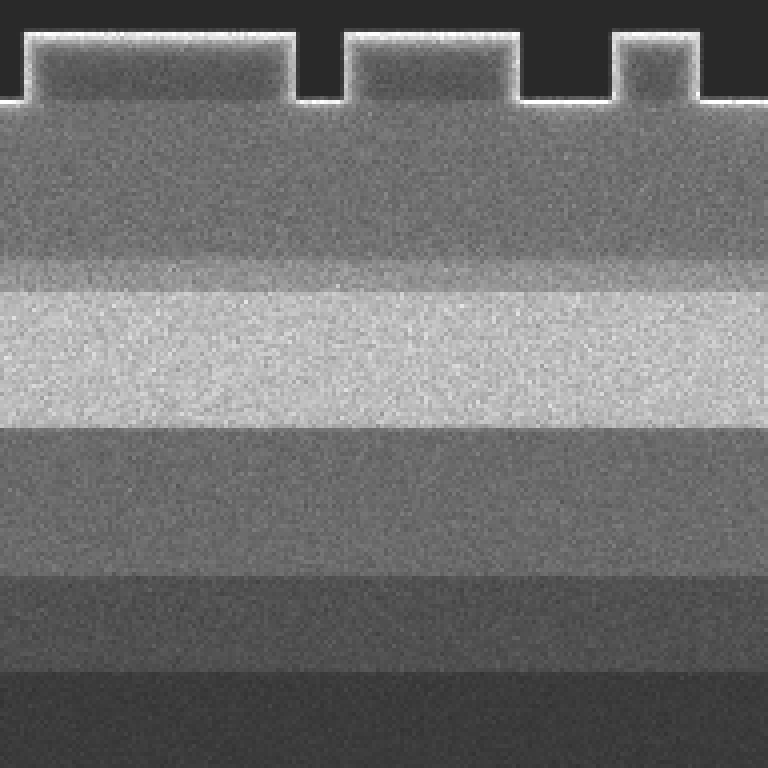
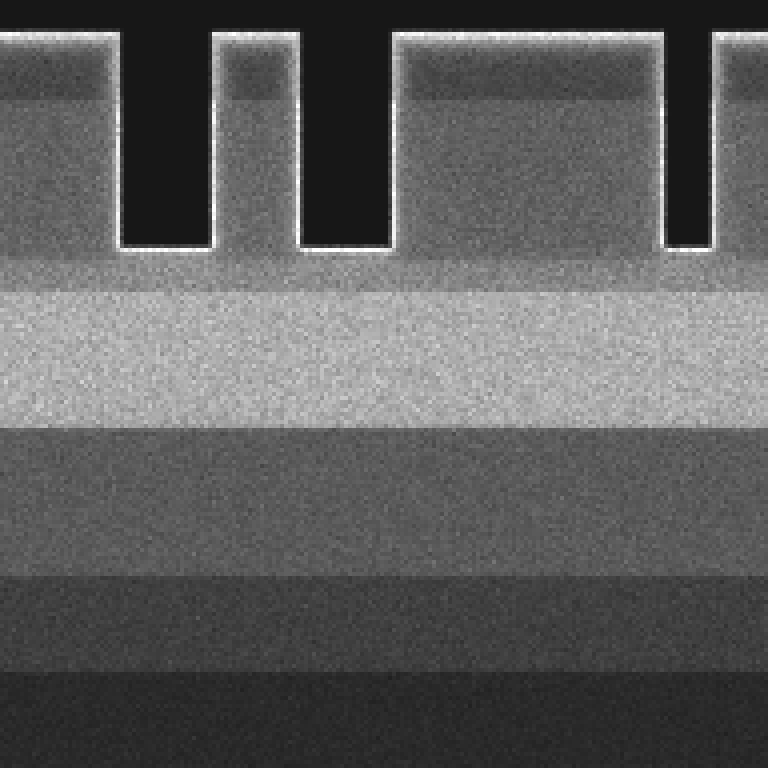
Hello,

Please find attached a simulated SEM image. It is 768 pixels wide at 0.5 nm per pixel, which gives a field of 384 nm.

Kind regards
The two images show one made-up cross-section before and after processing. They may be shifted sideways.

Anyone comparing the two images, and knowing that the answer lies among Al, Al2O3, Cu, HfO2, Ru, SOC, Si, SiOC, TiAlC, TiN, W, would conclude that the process removed Ru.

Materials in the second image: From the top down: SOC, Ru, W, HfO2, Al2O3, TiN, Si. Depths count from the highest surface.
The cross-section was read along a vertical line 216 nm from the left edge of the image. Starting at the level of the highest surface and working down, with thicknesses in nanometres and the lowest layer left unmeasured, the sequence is SOC 34, Ru 80, W 16, HfO2 68, Al2O3 74, TiN 48, Si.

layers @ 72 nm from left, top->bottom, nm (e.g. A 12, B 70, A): empty 108, Ru 6, W 16, HfO2 68, Al2O3 74, TiN 48, Si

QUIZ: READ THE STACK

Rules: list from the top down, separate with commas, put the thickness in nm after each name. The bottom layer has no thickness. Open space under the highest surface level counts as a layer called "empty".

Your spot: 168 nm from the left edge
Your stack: empty 108, Ru 6, W 16, HfO2 68, Al2O3 74, TiN 48, Si